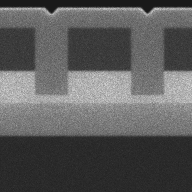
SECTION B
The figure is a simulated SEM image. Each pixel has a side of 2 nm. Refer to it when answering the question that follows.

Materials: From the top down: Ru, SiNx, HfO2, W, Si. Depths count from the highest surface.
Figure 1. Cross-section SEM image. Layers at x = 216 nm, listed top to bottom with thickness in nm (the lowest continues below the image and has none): Ru 40, SiNx 86, HfO2 64, W 66, Si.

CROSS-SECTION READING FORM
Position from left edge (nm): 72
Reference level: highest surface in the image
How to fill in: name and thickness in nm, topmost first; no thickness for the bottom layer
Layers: Ru 174, HfO2 16, W 66, Si